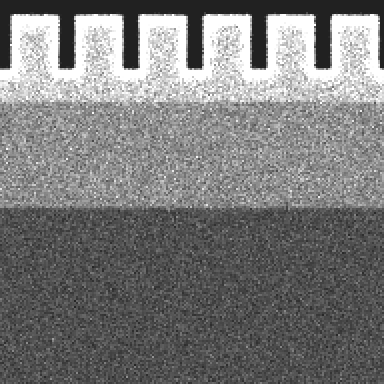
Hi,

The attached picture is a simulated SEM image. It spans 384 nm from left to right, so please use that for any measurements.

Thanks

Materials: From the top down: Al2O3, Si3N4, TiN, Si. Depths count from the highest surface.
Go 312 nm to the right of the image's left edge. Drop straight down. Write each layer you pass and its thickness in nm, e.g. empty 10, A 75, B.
Al2O3 86, Si3N4 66, TiN 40, Si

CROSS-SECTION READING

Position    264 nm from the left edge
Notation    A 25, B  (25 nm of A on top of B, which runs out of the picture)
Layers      empty 54, Al2O3 32, Si3N4 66, TiN 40, Si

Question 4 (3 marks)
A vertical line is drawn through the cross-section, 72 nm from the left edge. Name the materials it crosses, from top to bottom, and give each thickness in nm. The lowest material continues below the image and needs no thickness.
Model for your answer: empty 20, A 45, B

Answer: empty 54, Al2O3 32, Si3N4 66, TiN 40, Si